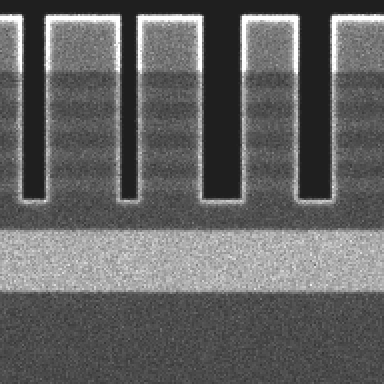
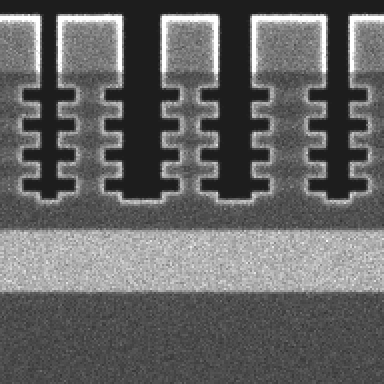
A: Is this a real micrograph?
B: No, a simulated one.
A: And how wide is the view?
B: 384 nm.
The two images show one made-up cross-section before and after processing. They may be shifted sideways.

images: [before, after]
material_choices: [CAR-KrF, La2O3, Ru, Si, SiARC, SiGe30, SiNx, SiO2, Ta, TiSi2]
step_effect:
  removed: SiGe30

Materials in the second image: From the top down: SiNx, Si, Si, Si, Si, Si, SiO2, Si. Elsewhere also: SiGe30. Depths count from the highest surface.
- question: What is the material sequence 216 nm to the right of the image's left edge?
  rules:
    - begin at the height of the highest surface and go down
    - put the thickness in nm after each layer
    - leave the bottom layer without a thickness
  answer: SiNx 56, Si 16, empty 14, Si 16, empty 14, Si 16, empty 14, Si 16, empty 14, Si 38, SiO2 62, Si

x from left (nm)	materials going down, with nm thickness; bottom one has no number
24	SiNx 56, Si 16, empty 14, Si 16, empty 14, Si 16, empty 14, Si 16, empty 14, Si 38, SiO2 62, Si